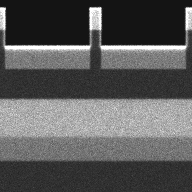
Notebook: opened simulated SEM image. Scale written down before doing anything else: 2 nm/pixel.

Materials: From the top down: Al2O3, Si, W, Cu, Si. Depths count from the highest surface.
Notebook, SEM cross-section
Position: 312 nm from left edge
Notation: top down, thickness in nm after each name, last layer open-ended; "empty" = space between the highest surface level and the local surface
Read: empty 76, Al2O3 46, Si 60, W 76, Cu 48, Si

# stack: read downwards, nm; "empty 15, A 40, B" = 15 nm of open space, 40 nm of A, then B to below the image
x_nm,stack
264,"empty 76, Al2O3 46, Si 60, W 76, Cu 48, Si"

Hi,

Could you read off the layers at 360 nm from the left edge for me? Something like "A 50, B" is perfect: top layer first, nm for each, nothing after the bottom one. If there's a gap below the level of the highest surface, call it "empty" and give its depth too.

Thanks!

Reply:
empty 76, Al2O3 46, Si 60, W 76, Cu 48, Si